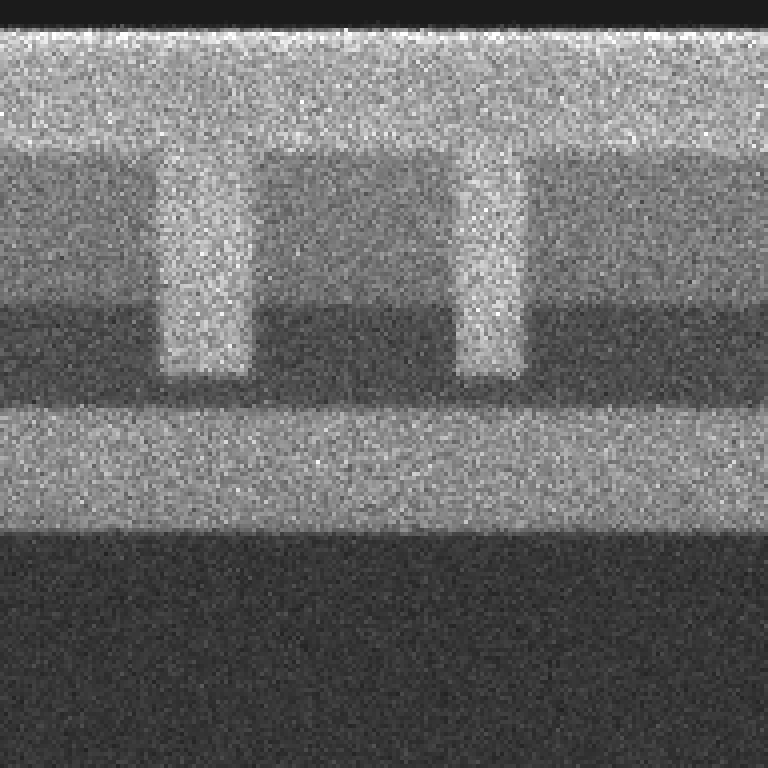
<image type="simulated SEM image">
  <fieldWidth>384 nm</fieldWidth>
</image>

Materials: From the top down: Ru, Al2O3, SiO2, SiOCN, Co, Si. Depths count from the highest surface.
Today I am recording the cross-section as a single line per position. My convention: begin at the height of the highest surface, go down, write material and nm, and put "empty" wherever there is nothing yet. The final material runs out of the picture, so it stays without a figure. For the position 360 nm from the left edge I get Ru 60, Al2O3 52, SiO2 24, SiOCN 52, Co 62, Si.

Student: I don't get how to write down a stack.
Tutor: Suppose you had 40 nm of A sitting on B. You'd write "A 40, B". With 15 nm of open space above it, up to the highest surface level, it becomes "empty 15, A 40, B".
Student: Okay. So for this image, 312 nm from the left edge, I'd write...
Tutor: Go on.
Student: Ru 60, Al2O3 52, SiO2 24, SiOCN 52, Co 62, Si